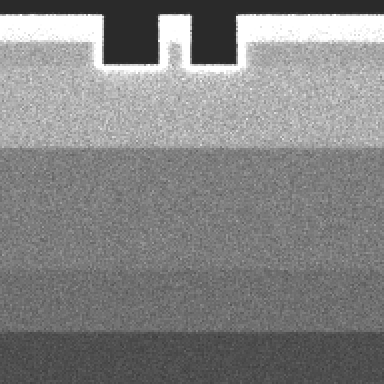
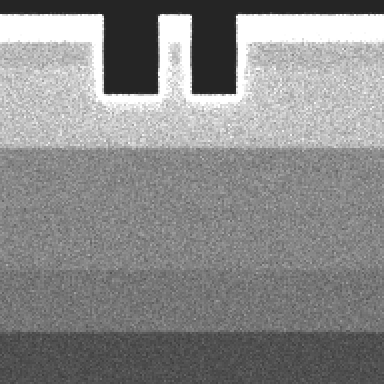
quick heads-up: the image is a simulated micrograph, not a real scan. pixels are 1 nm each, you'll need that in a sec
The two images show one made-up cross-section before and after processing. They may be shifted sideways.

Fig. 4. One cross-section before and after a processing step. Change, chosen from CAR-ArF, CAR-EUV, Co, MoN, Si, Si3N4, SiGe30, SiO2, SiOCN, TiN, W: Co removed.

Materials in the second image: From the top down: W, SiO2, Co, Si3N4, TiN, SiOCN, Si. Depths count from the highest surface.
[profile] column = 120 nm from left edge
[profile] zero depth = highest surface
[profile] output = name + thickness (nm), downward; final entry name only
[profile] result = empty 80, Co 52, Si3N4 60, TiN 62, SiOCN 62, Si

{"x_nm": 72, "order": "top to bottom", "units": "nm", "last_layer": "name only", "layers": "W 26, SiO2 24, Co 82, Si3N4 60, TiN 62, SiOCN 62, Si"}